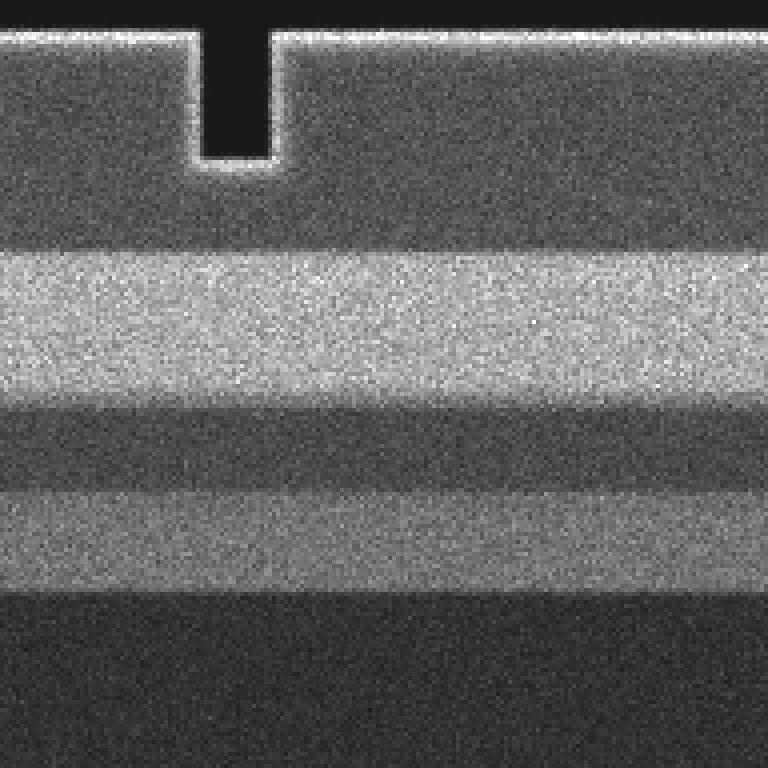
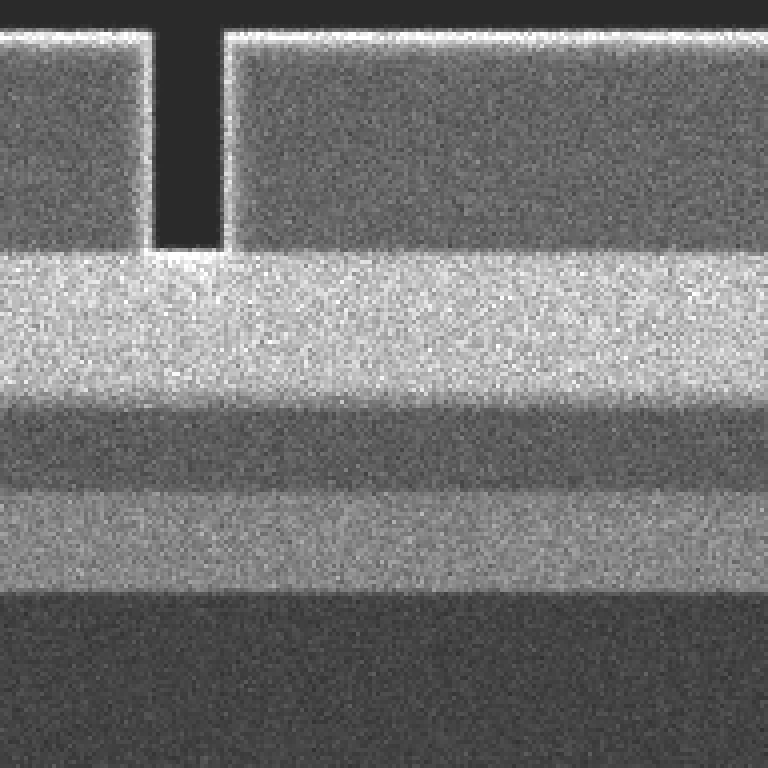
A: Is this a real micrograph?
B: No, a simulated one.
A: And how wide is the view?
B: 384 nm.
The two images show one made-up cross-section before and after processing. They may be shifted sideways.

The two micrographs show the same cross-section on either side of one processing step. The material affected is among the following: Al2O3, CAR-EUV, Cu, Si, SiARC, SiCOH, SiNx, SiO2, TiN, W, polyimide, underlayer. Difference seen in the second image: underlayer removed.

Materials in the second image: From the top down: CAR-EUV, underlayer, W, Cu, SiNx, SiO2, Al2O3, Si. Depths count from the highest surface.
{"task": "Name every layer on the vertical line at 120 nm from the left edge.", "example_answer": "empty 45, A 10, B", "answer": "CAR-EUV 64, underlayer 46, W 70, Cu 8, SiNx 42, SiO2 12, Al2O3 38, Si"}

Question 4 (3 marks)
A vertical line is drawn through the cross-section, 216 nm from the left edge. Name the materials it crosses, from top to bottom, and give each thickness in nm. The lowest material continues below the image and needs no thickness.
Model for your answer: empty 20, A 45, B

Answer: CAR-EUV 64, underlayer 46, W 70, Cu 8, SiNx 42, SiO2 12, Al2O3 38, Si